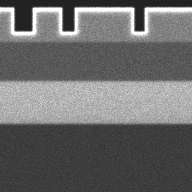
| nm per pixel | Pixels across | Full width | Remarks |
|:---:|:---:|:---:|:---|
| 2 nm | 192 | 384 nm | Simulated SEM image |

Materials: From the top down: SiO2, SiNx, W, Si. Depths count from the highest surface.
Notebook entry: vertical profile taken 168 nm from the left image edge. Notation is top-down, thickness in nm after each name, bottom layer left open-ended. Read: SiO2 68, SiNx 78, W 86, Si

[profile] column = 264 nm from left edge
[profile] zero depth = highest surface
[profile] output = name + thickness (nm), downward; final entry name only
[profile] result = SiO2 68, SiNx 78, W 86, Si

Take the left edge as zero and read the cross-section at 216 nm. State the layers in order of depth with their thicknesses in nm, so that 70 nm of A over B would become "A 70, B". SiO2 68, SiNx 78, W 86, Si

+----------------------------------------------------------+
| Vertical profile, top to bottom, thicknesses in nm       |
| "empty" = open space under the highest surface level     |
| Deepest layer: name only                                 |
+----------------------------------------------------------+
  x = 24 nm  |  SiO2 68, SiNx 78, W 86, Si